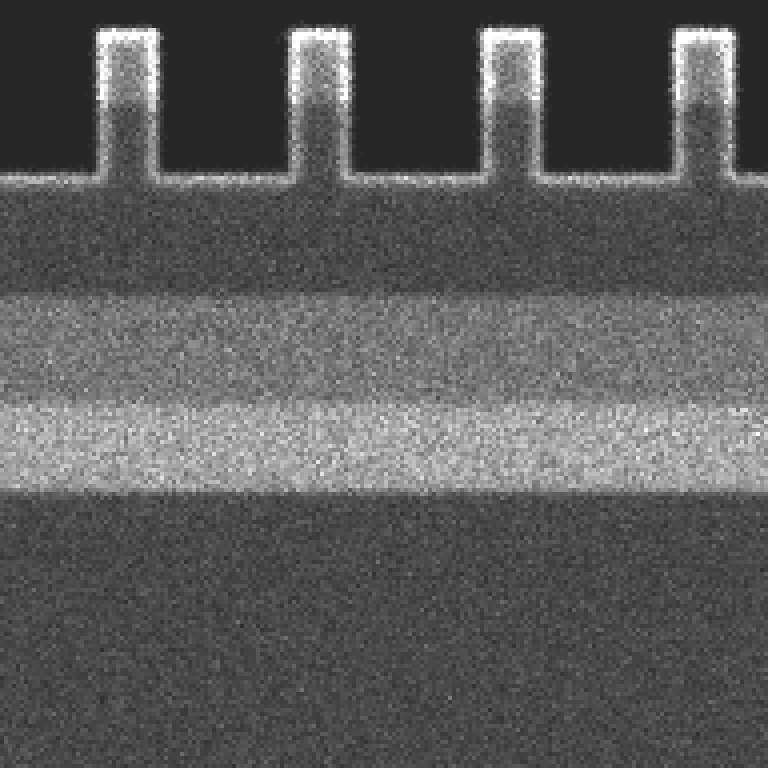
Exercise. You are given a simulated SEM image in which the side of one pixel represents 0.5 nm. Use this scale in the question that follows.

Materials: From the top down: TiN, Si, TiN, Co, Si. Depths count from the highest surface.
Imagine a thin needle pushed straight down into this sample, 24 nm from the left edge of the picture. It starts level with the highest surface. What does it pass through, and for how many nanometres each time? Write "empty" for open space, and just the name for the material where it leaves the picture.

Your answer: empty 72, Si 60, TiN 54, Co 44, Si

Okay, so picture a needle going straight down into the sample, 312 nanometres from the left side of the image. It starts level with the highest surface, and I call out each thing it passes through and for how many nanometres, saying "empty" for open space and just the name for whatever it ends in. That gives empty 72, Si 60, TiN 54, Co 44, Si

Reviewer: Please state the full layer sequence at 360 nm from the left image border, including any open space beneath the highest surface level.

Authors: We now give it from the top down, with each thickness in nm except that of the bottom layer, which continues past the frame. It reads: TiN 36, Si 96, TiN 54, Co 44, Si